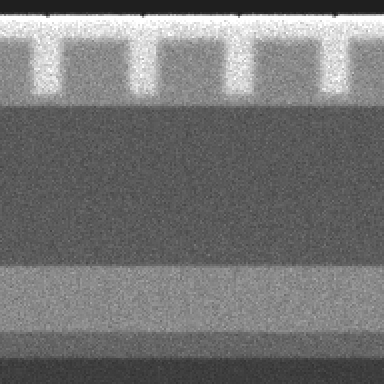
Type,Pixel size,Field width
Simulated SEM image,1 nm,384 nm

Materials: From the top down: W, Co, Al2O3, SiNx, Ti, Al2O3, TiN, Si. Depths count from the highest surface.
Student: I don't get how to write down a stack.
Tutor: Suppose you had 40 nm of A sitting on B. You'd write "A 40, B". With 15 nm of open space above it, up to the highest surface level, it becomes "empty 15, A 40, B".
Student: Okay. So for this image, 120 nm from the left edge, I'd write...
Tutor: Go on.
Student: W 22, Co 6, Al2O3 62, SiNx 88, Ti 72, Al2O3 66, TiN 26, Si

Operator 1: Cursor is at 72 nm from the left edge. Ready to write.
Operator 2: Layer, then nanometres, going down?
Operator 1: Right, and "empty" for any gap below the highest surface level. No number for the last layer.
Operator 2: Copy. W 22, Co 6, Al2O3 62, SiNx 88, Ti 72, Al2O3 66, TiN 26, Si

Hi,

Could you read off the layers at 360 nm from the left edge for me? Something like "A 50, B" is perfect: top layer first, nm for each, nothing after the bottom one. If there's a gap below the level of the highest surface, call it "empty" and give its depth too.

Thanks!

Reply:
W 22, Co 6, Al2O3 62, SiNx 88, Ti 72, Al2O3 66, TiN 26, Si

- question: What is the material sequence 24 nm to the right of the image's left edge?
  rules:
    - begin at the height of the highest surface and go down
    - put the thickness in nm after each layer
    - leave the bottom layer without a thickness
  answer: W 22, Co 6, Al2O3 62, SiNx 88, Ti 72, Al2O3 66, TiN 26, Si